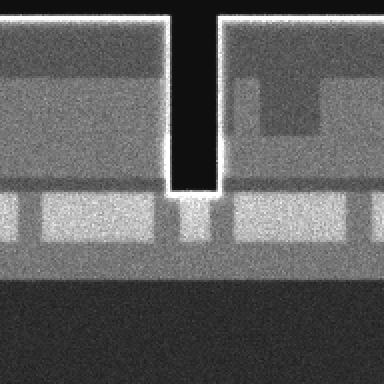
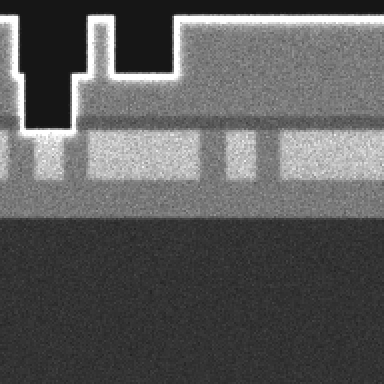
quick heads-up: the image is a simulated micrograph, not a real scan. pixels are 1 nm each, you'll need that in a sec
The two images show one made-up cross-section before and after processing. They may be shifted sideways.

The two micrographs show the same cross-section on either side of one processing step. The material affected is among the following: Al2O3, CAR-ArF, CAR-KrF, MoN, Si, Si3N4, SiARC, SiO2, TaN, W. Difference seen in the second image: SiARC removed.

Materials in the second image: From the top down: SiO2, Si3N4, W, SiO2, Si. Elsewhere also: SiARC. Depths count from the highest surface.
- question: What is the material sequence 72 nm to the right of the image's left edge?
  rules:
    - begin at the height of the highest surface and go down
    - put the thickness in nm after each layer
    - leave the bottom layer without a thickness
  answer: empty 58, SiO2 42, Si3N4 14, SiO2 88, Si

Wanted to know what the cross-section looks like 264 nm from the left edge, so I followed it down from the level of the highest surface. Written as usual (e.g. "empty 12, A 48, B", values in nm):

SiO2 100, Si3N4 14, SiO2 88, Si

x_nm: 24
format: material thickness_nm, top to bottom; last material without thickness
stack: empty 114, SiO2 88, Si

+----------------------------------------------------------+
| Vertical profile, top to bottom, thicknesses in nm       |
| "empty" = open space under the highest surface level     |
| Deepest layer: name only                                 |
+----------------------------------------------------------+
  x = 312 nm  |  SiO2 100, Si3N4 14, W 50, SiO2 38, Si